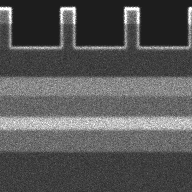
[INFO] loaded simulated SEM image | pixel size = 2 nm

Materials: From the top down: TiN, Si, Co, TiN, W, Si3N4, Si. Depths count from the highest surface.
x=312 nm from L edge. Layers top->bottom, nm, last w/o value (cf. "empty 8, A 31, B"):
empty 78, Si 60, Co 38, TiN 42, W 26, Si3N4 44, Si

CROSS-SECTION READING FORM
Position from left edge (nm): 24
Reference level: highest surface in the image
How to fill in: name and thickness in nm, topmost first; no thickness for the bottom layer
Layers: empty 78, Si 60, Co 38, TiN 42, W 26, Si3N4 44, Si